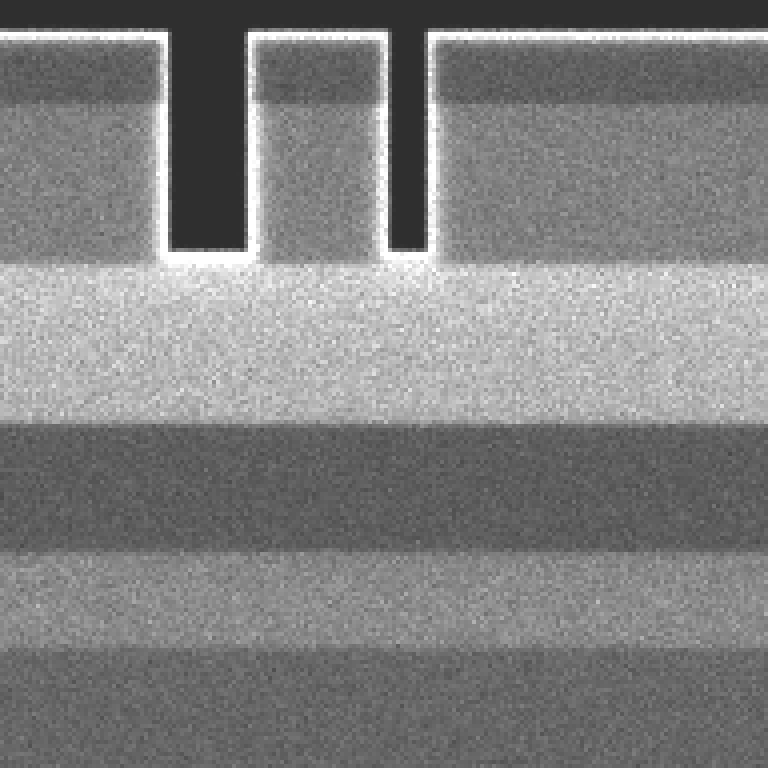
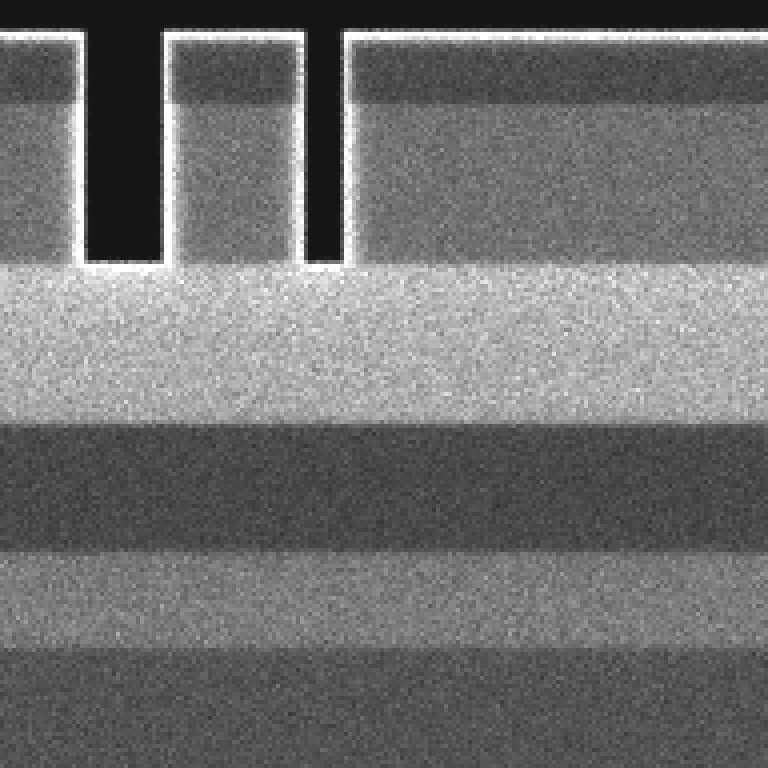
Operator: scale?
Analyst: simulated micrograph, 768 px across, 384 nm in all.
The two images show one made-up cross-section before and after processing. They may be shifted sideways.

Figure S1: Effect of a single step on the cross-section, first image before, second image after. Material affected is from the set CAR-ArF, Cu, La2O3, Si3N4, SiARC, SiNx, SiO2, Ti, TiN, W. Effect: removed SiO2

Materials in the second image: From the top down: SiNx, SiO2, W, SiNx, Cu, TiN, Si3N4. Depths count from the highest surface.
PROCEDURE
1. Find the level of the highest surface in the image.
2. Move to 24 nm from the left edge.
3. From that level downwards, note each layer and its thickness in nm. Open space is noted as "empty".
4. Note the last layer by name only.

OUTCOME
SiNx 36, SiO2 80, W 80, SiNx 64, Cu 48, TiN 30, Si3N4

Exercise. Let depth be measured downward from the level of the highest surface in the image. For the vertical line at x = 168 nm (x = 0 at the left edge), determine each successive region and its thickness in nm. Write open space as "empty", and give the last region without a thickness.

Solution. empty 116, W 80, SiNx 64, Cu 48, TiN 30, Si3N4